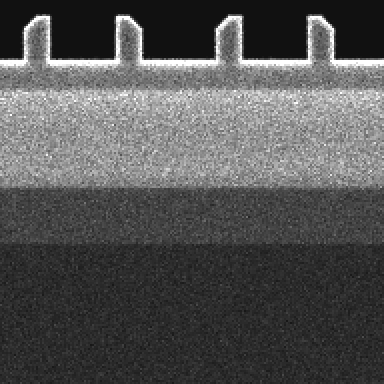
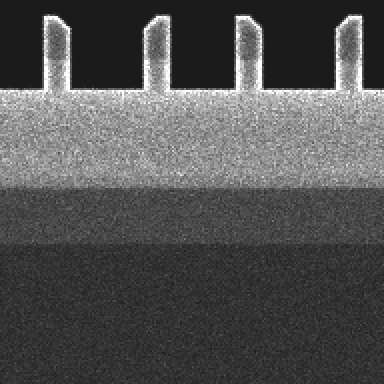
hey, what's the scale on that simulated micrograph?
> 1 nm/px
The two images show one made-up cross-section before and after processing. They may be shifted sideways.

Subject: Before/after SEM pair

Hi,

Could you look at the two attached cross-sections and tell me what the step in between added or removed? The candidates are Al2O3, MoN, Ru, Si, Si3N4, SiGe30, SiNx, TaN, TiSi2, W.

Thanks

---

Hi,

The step removed Al2O3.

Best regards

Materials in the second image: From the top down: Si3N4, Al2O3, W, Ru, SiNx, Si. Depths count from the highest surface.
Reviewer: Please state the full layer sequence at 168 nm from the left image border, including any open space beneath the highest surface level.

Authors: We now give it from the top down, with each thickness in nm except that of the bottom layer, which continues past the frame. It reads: Si3N4 44, Al2O3 30, W 86, Ru 12, SiNx 56, Si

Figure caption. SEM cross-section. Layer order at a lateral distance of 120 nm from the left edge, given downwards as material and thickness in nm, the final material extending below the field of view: empty 74, W 86, Ru 12, SiNx 56, Si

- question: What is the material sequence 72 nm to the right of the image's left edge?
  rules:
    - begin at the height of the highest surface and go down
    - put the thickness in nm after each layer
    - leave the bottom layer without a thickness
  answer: empty 74, W 86, Ru 12, SiNx 56, Si